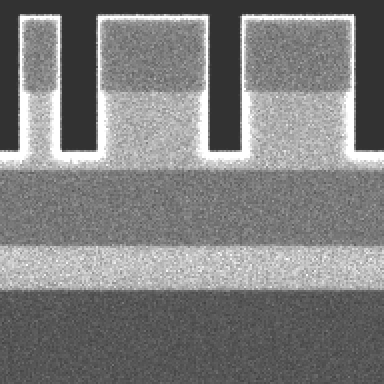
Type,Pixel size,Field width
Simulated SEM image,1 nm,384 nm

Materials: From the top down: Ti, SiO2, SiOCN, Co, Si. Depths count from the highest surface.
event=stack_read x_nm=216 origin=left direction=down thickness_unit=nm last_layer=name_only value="empty 136, SiO2 18, SiOCN 76, Co 44, Si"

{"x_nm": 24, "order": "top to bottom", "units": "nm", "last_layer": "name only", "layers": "Ti 76, SiO2 78, SiOCN 76, Co 44, Si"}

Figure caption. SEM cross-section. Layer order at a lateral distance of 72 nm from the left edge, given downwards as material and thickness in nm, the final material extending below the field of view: empty 136, SiO2 18, SiOCN 76, Co 44, Si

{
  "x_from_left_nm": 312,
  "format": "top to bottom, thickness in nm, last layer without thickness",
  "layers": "Ti 76, SiO2 78, SiOCN 76, Co 44, Si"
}